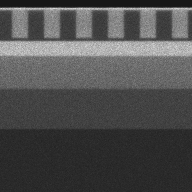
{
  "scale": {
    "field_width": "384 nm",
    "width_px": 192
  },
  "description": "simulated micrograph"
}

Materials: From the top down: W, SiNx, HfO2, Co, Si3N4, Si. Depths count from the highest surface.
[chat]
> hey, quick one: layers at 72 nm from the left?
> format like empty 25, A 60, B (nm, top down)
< SiNx 66, HfO2 30, Co 66, Si3N4 80, Si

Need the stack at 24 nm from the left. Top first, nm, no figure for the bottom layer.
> W 60, SiNx 6, HfO2 30, Co 66, Si3N4 80, Si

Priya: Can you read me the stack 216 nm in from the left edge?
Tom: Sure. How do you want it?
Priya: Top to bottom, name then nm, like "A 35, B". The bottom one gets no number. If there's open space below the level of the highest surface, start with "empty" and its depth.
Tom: W 60, SiNx 6, HfO2 30, Co 66, Si3N4 80, Si